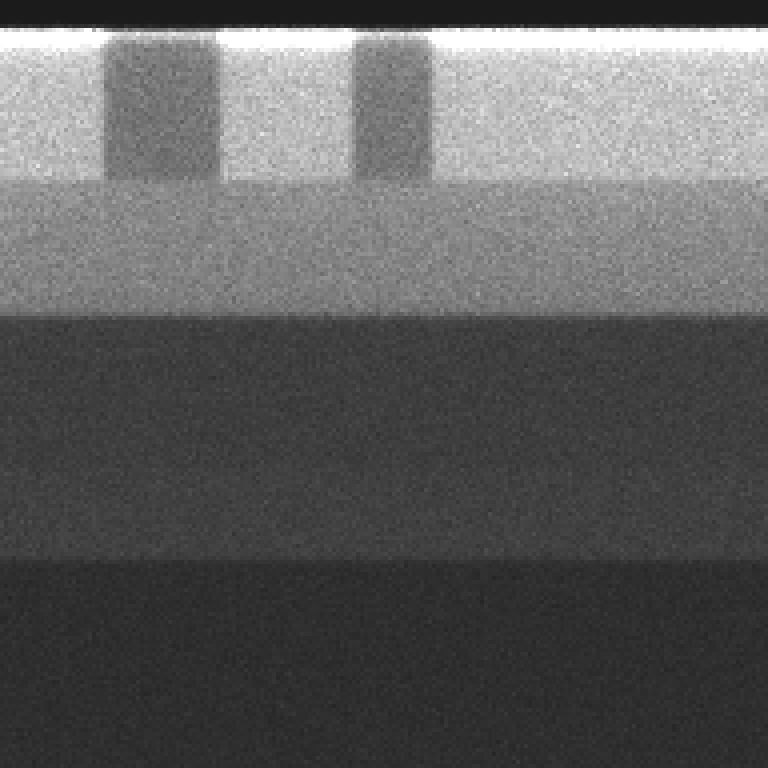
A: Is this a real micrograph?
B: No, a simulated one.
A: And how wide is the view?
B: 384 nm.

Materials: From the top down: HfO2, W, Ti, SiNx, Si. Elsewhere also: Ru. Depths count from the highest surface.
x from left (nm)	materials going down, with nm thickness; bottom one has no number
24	HfO2 74, W 68, Ti 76, SiNx 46, Si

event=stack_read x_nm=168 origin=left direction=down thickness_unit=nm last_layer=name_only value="HfO2 74, W 68, Ti 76, SiNx 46, Si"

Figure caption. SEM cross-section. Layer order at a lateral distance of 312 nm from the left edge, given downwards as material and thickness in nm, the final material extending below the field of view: HfO2 74, W 68, Ti 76, SiNx 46, Si